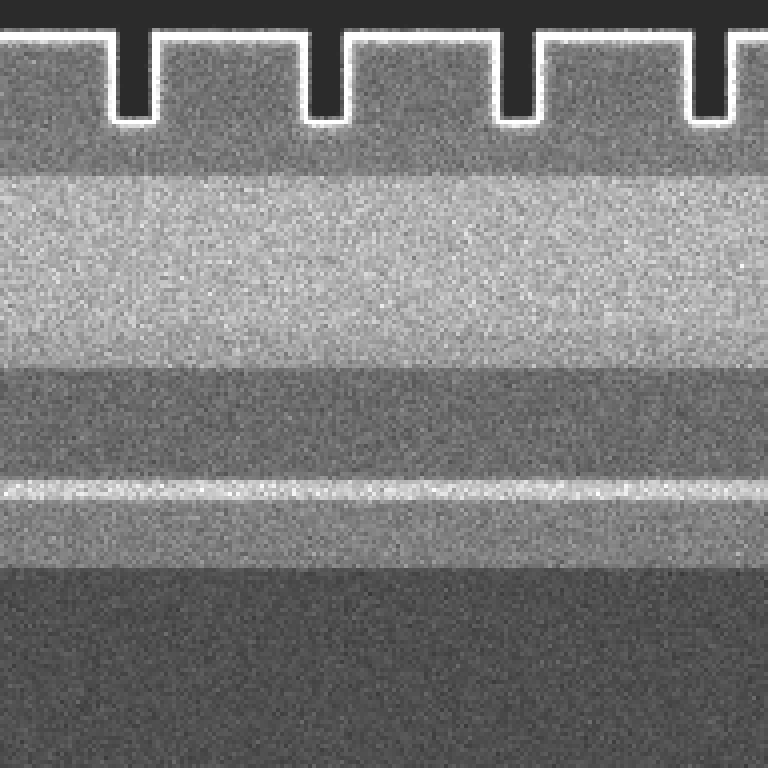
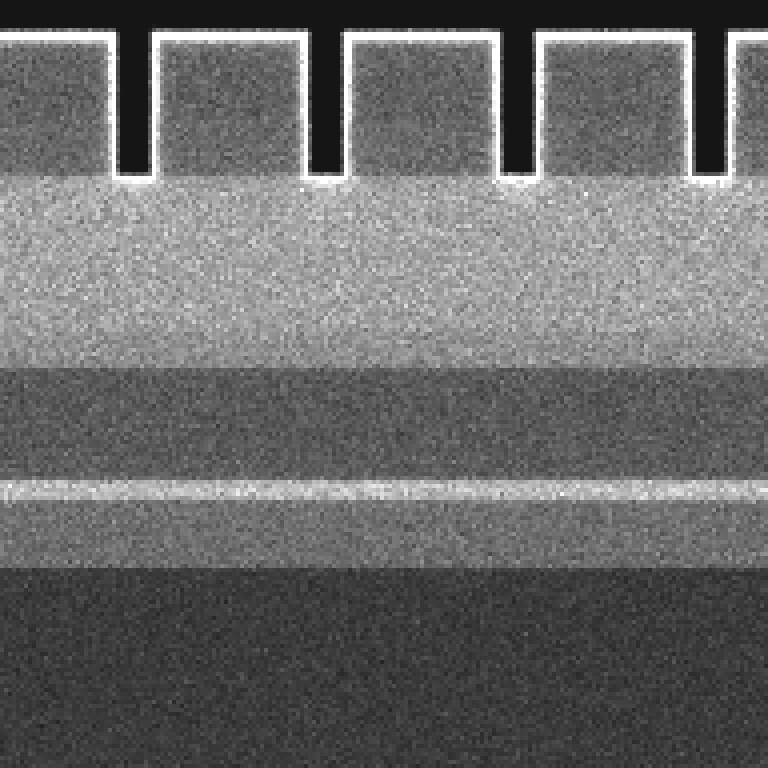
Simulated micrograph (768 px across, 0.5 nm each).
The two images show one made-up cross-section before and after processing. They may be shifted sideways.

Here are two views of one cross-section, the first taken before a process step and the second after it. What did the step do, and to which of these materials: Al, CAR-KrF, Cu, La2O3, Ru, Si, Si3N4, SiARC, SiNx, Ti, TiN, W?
It removed TiN.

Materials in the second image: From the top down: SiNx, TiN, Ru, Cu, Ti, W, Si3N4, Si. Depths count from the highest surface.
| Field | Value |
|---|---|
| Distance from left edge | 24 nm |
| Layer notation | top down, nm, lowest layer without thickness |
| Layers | SiNx 44, TiN 28, Ru 78, Cu 18, Ti 56, W 10, Si3N4 34, Si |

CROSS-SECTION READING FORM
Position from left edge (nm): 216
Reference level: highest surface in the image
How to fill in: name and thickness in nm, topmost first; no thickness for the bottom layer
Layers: SiNx 44, TiN 28, Ru 78, Cu 18, Ti 56, W 10, Si3N4 34, Si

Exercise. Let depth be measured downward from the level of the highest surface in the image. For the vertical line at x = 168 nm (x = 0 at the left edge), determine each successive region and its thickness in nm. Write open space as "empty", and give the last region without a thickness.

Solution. empty 72, Ru 78, Cu 18, Ti 56, W 10, Si3N4 34, Si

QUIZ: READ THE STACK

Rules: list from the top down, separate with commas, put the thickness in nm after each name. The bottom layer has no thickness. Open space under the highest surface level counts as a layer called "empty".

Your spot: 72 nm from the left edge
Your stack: empty 72, Ru 78, Cu 18, Ti 56, W 10, Si3N4 34, Si